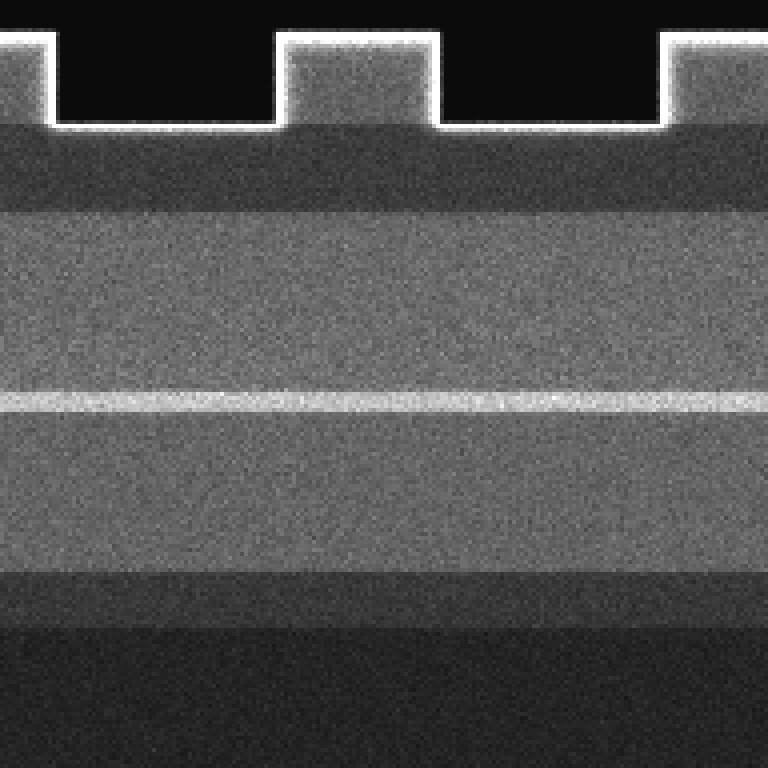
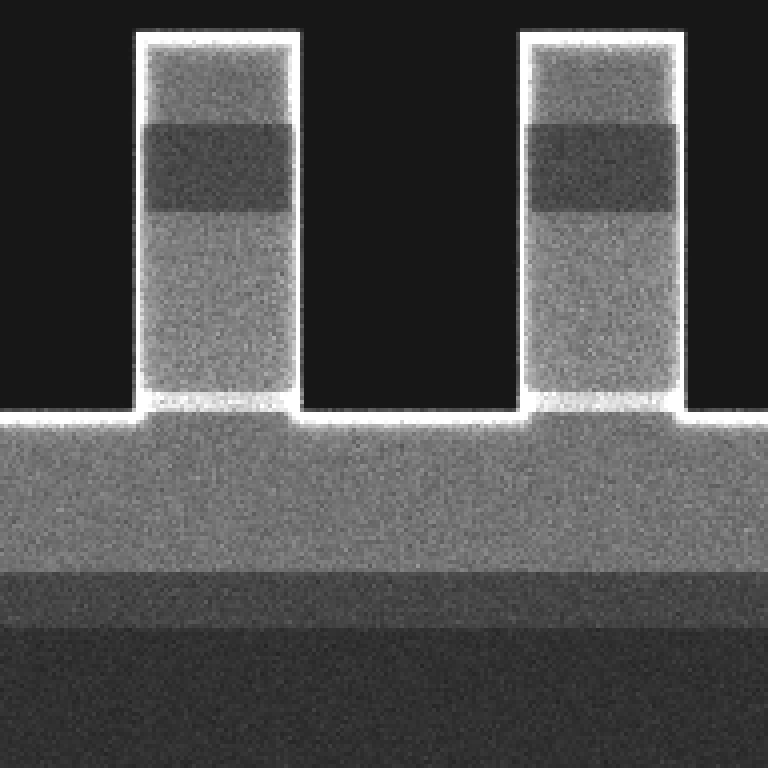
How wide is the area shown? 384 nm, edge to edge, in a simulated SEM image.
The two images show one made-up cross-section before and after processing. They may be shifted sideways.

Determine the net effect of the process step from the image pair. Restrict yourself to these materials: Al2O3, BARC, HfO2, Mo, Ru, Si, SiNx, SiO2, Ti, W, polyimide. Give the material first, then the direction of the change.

HfO2 and Ru and SiNx: removed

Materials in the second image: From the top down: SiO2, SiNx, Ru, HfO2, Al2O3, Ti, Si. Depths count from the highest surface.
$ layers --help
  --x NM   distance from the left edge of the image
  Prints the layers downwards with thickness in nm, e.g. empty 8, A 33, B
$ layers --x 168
empty 190, Al2O3 80, Ti 28, Si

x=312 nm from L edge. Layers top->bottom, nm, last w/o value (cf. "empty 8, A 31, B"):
SiO2 46, SiNx 44, Ru 90, HfO2 10, Al2O3 80, Ti 28, Si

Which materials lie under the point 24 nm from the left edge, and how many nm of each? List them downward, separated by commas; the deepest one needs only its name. empty 190, Al2O3 80, Ti 28, Si